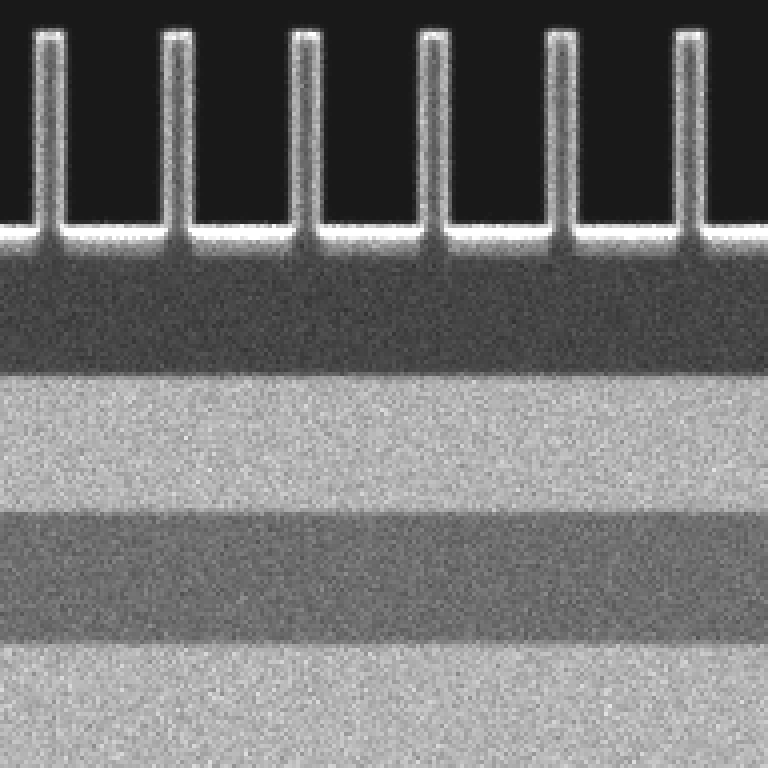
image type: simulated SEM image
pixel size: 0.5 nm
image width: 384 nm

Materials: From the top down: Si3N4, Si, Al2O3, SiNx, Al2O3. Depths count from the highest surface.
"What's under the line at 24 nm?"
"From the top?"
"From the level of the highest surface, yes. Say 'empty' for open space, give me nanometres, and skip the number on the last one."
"Si 172, Al2O3 68, SiNx 66, Al2O3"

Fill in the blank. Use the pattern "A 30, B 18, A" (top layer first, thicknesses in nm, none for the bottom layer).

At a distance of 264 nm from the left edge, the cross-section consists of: empty 98, Si3N4 14, Si 60, Al2O3 68, SiNx 66, Al2O3